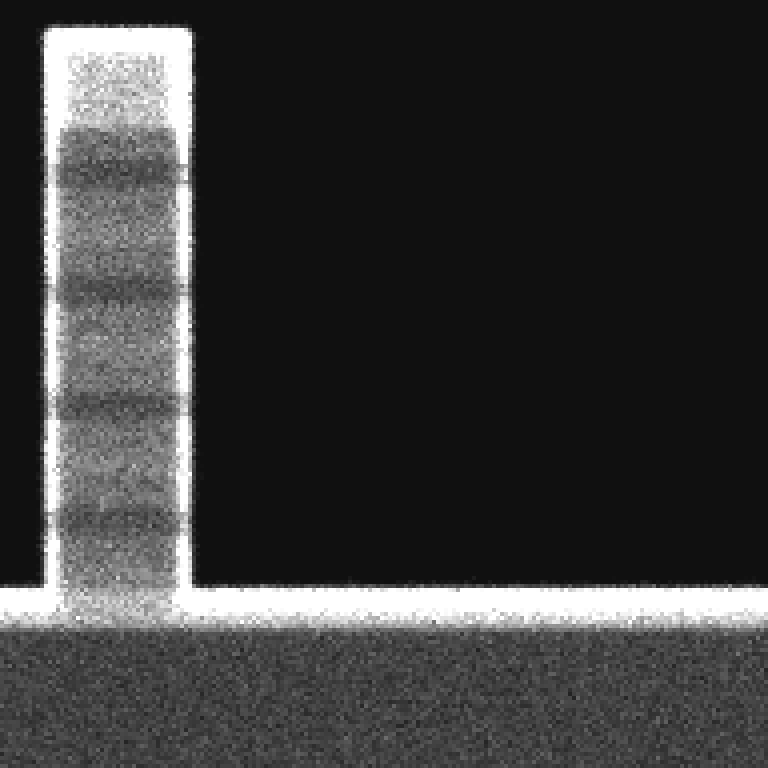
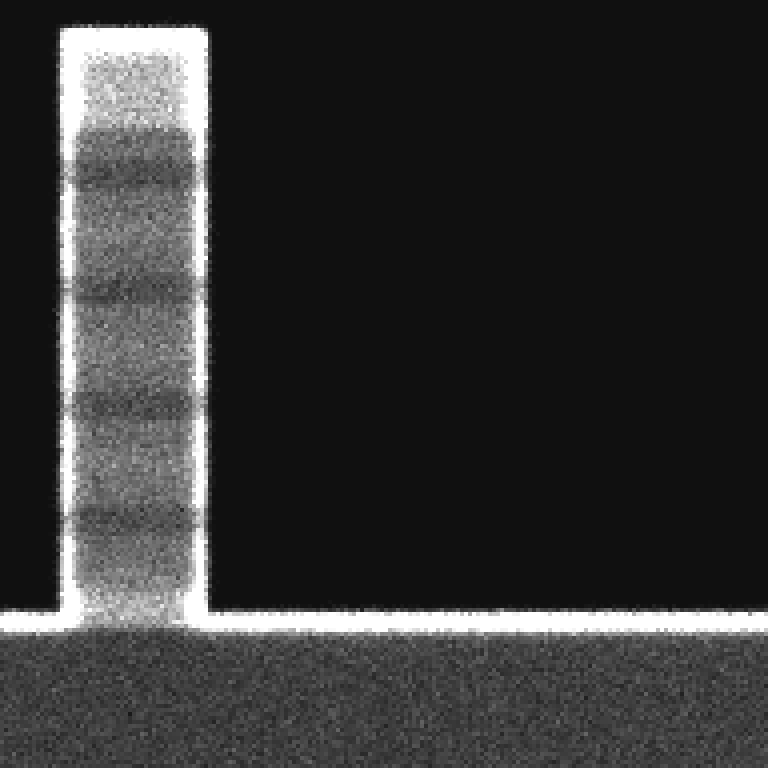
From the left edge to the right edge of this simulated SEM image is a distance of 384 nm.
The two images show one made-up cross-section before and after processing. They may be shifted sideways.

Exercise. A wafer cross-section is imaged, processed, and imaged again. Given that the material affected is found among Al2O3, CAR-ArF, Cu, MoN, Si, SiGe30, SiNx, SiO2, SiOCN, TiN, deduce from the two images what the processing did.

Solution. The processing removed SiO2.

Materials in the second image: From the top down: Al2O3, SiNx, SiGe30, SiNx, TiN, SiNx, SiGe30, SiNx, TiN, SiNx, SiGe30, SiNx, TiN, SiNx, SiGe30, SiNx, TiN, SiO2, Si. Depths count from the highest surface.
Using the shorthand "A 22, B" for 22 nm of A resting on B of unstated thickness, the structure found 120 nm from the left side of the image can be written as empty 292, SiO2 6, Si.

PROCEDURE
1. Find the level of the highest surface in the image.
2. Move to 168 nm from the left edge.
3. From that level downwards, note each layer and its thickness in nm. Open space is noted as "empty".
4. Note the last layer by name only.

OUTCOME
empty 292, SiO2 6, Si